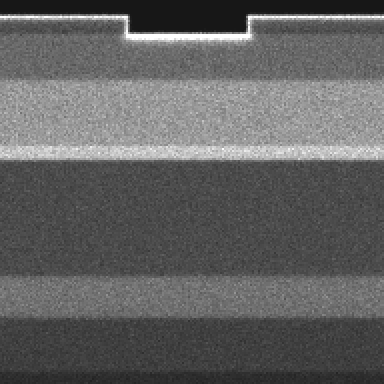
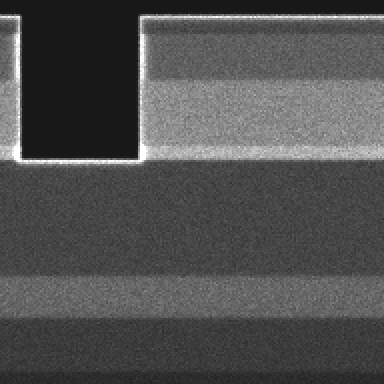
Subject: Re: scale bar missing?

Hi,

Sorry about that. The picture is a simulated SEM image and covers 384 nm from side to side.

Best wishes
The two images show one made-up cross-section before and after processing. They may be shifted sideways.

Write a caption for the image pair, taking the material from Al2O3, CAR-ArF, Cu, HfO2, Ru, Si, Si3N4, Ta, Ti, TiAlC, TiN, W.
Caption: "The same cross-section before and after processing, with Al2O3 and HfO2 and W removed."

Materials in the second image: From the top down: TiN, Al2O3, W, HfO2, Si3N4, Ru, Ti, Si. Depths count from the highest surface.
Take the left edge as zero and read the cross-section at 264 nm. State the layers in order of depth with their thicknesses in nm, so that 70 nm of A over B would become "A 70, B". TiN 18, Al2O3 46, W 66, HfO2 14, Si3N4 116, Ru 42, Ti 54, Si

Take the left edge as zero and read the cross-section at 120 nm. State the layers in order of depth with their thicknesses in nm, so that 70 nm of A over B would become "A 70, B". empty 144, Si3N4 116, Ru 42, Ti 54, Si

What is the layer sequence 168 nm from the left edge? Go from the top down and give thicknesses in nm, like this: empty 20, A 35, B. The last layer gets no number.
TiN 18, Al2O3 46, W 66, HfO2 14, Si3N4 116, Ru 42, Ti 54, Si